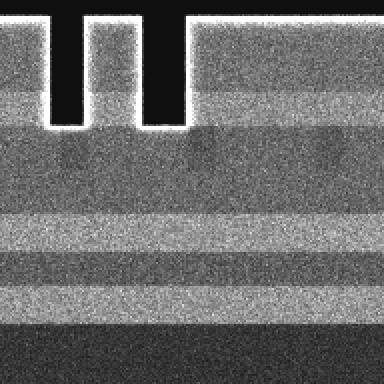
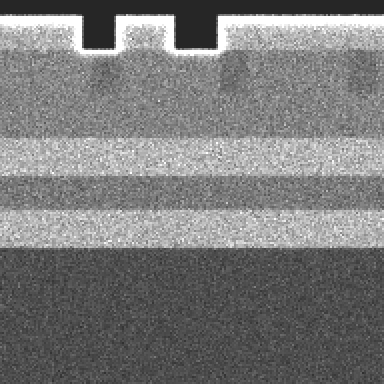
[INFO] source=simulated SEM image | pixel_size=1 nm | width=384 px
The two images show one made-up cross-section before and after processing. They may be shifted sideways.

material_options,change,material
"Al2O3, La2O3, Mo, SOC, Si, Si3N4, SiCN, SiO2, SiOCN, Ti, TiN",removed,SOC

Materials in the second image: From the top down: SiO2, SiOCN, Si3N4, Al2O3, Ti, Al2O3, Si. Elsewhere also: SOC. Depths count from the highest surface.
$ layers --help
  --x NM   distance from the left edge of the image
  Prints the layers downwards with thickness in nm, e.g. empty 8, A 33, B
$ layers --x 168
SiO2 34, Si3N4 88, Al2O3 38, Ti 34, Al2O3 38, Si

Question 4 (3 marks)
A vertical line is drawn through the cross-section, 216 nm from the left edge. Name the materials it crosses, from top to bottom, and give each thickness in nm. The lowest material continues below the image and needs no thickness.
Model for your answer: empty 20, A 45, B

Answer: empty 34, Si3N4 88, Al2O3 38, Ti 34, Al2O3 38, Si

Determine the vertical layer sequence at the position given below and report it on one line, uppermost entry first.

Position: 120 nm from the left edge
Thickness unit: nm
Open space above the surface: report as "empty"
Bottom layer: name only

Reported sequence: SiO2 34, Si3N4 88, Al2O3 38, Ti 34, Al2O3 38, Si